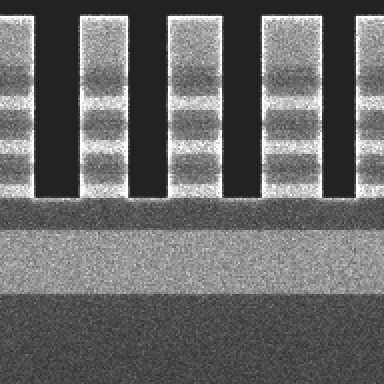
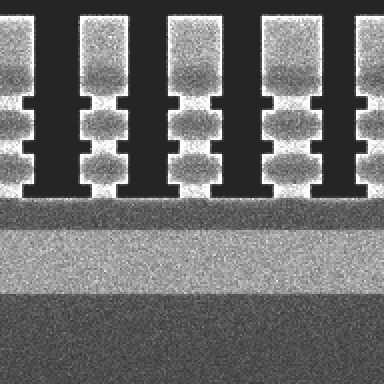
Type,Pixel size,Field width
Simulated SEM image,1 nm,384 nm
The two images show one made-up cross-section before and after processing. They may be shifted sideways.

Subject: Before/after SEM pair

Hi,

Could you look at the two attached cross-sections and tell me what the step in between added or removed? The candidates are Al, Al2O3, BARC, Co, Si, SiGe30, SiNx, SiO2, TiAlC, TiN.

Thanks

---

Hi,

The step removed Co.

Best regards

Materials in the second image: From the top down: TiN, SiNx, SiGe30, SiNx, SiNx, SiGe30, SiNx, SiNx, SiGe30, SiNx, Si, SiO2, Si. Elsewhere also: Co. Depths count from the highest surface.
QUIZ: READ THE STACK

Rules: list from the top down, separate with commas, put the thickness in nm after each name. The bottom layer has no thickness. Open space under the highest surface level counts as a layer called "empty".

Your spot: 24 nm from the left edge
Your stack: TiN 50, SiNx 10, SiGe30 10, SiNx 10, empty 14, SiNx 10, SiGe30 10, SiNx 10, empty 14, SiNx 10, SiGe30 10, SiNx 10, empty 14, Si 32, SiO2 64, Si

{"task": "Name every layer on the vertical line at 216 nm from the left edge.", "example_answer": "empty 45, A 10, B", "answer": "TiN 50, SiNx 10, SiGe30 10, SiNx 10, empty 14, SiNx 10, SiGe30 10, SiNx 10, empty 14, SiNx 10, SiGe30 10, SiNx 10, empty 14, Si 32, SiO2 64, Si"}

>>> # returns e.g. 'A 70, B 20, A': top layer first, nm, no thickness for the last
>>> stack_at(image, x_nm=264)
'TiN 50, SiNx 10, SiGe30 10, SiNx 10, empty 14, SiNx 10, SiGe30 10, SiNx 10, empty 14, SiNx 10, SiGe30 10, SiNx 10, empty 14, Si 32, SiO2 64, Si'